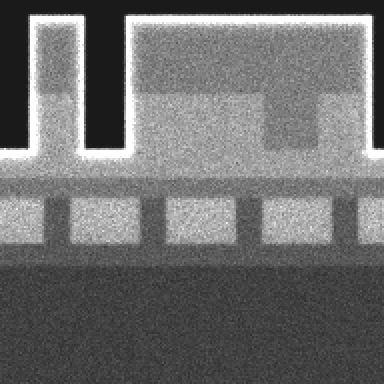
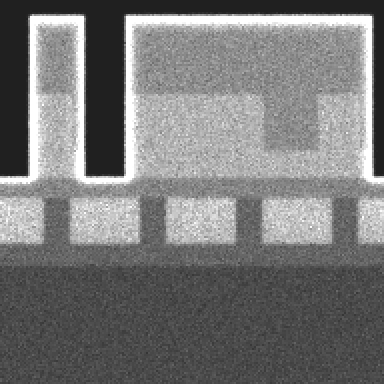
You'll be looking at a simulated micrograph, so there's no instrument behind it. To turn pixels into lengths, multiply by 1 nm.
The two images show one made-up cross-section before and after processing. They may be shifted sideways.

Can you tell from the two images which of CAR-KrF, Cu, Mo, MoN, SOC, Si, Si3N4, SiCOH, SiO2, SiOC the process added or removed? Yes, it removed SiO2.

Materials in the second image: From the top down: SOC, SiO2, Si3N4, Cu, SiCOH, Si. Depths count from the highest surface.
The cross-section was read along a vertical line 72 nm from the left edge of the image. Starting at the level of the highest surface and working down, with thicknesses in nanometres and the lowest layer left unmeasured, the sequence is SOC 134, SiO2 28, Si3N4 20, Cu 46, SiCOH 22, Si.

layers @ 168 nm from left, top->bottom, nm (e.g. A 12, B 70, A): SOC 78, SiO2 84, Si3N4 20, Cu 46, SiCOH 22, Si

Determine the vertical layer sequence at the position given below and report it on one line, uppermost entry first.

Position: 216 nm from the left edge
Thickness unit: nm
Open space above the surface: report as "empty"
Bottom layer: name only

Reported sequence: SOC 78, SiO2 84, Si3N4 20, Cu 46, SiCOH 22, Si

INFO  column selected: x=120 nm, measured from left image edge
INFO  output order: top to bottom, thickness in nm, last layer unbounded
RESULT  empty 162, Si3N4 20, Cu 46, SiCOH 22, Si